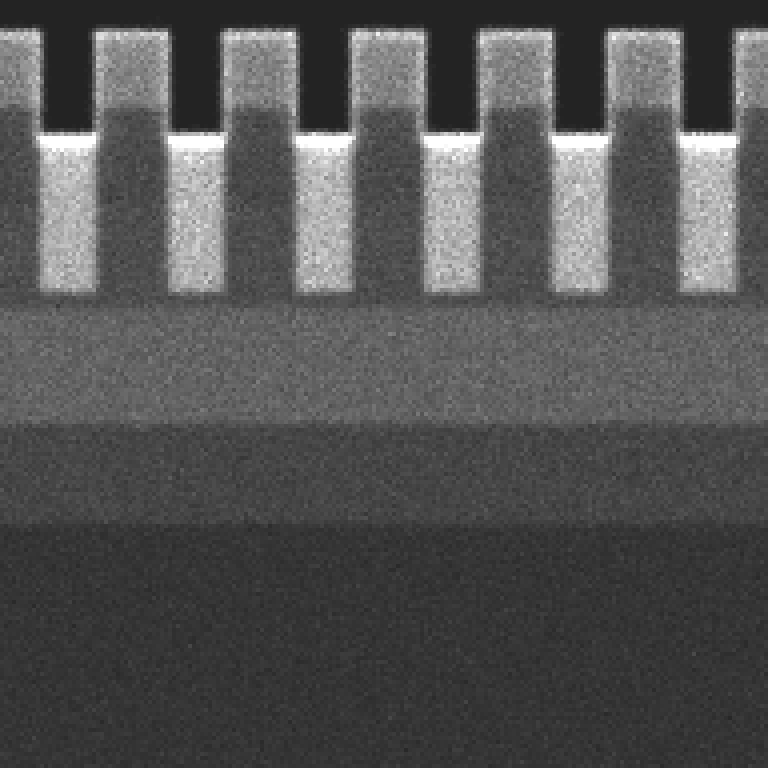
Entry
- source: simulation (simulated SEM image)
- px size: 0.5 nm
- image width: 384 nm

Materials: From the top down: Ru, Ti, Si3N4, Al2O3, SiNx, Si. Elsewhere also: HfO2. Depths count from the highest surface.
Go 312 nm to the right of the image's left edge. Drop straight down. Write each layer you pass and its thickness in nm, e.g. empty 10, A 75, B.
Ru 38, Ti 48, Si3N4 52, Al2O3 58, SiNx 50, Si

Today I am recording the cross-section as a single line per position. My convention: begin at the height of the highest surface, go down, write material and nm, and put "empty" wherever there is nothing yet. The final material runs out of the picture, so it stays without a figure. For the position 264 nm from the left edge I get Ru 38, Ti 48, Si3N4 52, Al2O3 58, SiNx 50, Si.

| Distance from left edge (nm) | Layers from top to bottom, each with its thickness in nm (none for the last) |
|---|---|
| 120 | Ru 38, Ti 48, Si3N4 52, Al2O3 58, SiNx 50, Si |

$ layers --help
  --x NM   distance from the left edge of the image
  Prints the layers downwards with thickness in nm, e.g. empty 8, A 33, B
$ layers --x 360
empty 52, HfO2 78, Si3N4 8, Al2O3 58, SiNx 50, Si